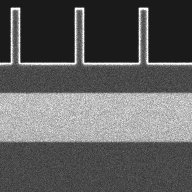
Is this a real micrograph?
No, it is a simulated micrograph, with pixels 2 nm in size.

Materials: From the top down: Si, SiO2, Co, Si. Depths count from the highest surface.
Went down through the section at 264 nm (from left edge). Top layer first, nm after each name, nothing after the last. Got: empty 110, Si 60, SiO2 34, Co 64, Si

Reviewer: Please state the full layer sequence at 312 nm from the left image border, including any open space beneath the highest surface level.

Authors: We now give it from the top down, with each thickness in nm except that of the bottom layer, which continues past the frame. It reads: empty 110, Si 60, SiO2 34, Co 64, Si